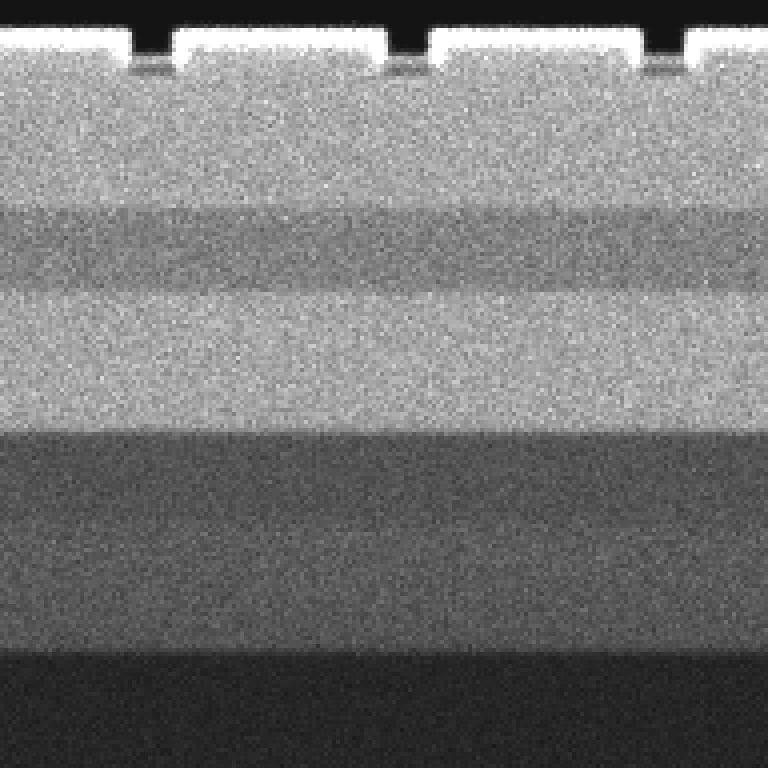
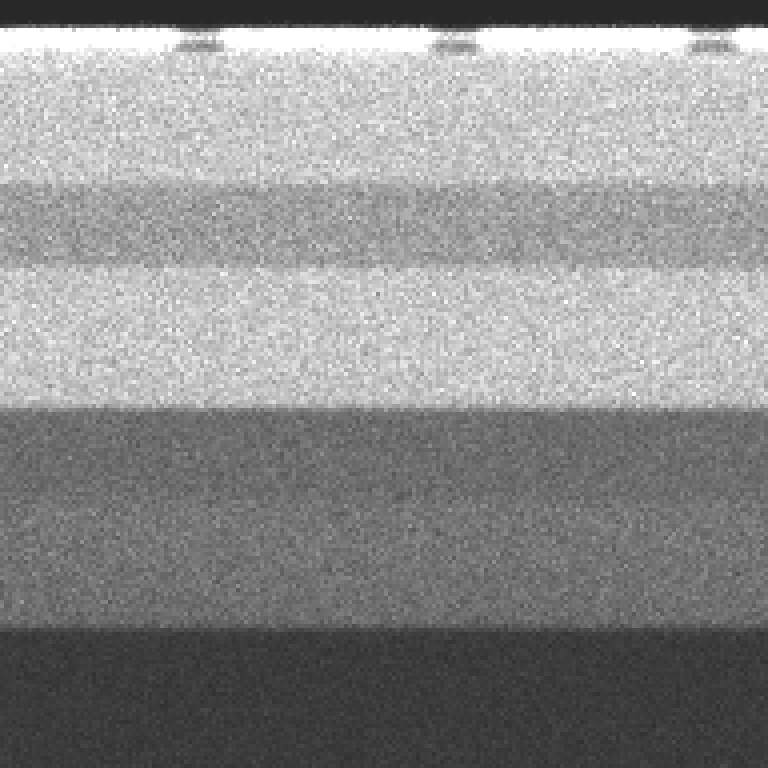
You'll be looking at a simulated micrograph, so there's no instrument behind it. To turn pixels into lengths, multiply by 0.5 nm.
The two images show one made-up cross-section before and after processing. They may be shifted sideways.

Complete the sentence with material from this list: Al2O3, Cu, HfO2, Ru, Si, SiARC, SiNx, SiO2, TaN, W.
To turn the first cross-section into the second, HfO2 must be removed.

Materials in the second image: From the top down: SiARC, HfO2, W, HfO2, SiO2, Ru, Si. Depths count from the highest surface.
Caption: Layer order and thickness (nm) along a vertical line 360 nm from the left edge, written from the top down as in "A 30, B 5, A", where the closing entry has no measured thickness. SiARC 10, HfO2 66, W 42, HfO2 70, SiO2 46, Ru 64, Si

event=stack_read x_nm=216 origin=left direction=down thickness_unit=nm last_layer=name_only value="SiARC 10, HfO2 66, W 42, HfO2 70, SiO2 46, Ru 64, Si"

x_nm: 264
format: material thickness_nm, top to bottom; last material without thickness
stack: HfO2 76, W 42, HfO2 70, SiO2 46, Ru 64, Si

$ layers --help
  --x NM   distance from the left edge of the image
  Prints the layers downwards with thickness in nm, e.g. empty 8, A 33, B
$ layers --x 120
HfO2 76, W 42, HfO2 70, SiO2 46, Ru 64, Si